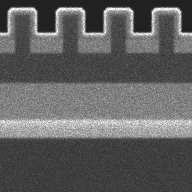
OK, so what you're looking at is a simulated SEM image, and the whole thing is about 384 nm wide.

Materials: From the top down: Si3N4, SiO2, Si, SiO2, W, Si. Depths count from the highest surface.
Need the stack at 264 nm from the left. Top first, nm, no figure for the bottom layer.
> empty 6, Si3N4 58, SiO2 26, Si 60, SiO2 74, W 36, Si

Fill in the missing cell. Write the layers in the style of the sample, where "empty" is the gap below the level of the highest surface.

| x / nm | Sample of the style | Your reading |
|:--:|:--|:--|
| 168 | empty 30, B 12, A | empty 6, Si3N4 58, SiO2 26, Si 60, SiO2 74, W 36, Si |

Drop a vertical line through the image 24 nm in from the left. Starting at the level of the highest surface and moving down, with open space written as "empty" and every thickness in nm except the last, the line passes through Si3N4 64, SiO2 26, Si 60, SiO2 74, W 36, Si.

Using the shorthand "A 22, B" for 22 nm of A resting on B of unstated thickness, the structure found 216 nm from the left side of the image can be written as Si3N4 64, SiO2 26, Si 60, SiO2 74, W 36, Si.